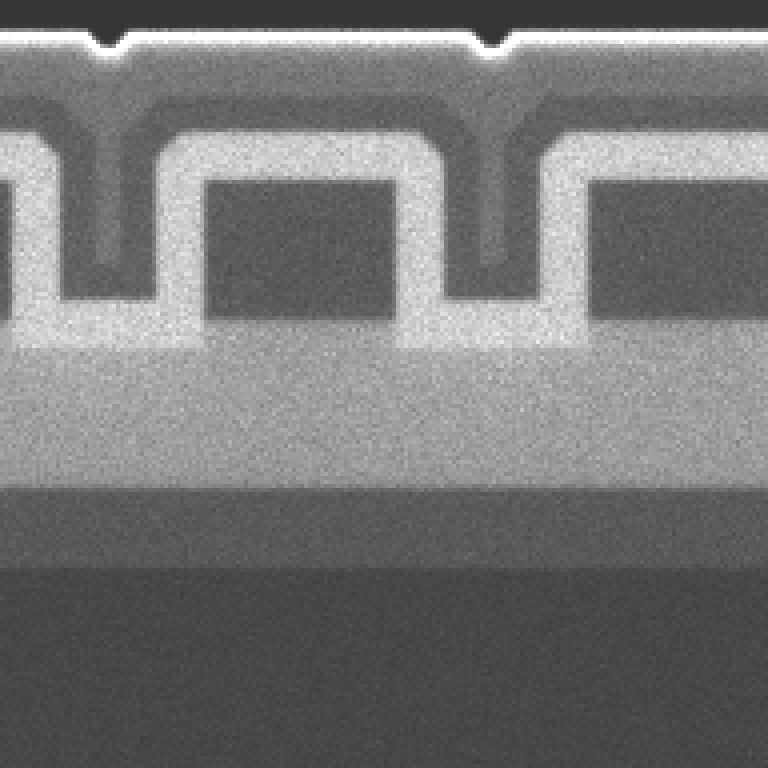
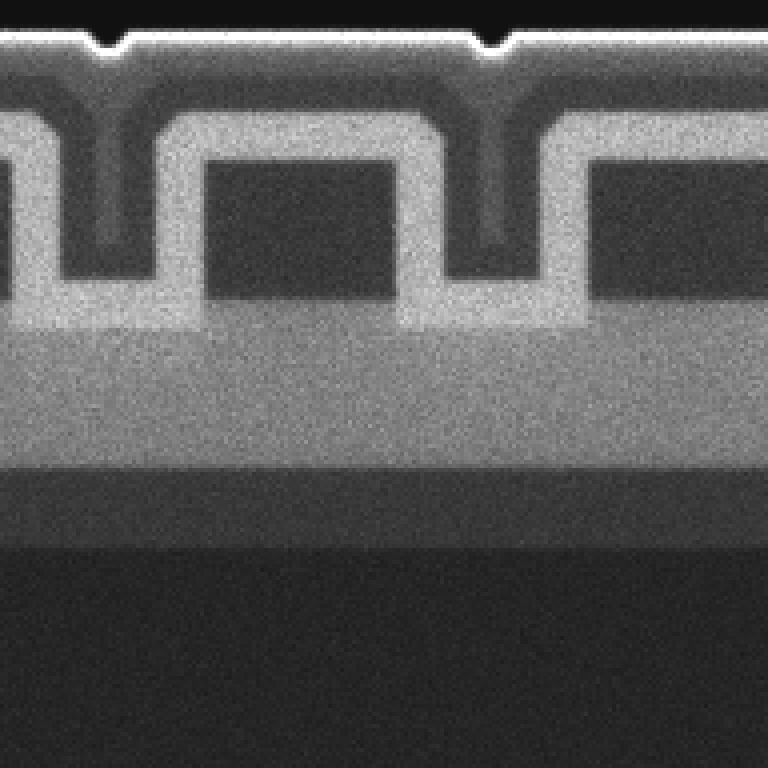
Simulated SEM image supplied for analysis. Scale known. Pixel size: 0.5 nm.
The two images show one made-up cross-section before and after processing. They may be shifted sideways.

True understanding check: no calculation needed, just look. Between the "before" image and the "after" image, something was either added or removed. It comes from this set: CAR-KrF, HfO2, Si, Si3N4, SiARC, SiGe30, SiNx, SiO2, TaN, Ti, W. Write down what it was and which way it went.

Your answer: SiO2 (removed)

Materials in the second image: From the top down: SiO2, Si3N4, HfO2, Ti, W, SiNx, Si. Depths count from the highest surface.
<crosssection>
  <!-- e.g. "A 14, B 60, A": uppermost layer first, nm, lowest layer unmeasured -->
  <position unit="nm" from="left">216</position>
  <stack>SiO2 22, Si3N4 26, HfO2 100, W 70, SiNx 40, Si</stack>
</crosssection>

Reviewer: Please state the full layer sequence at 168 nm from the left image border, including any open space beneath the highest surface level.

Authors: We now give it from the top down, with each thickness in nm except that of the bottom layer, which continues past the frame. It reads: SiO2 22, Si3N4 18, HfO2 24, Ti 70, W 84, SiNx 40, Si